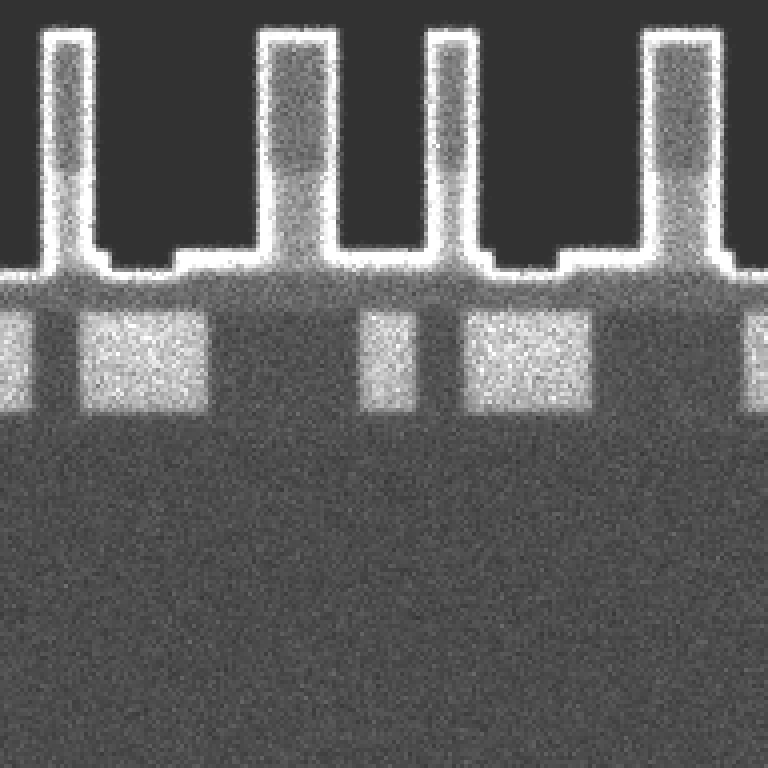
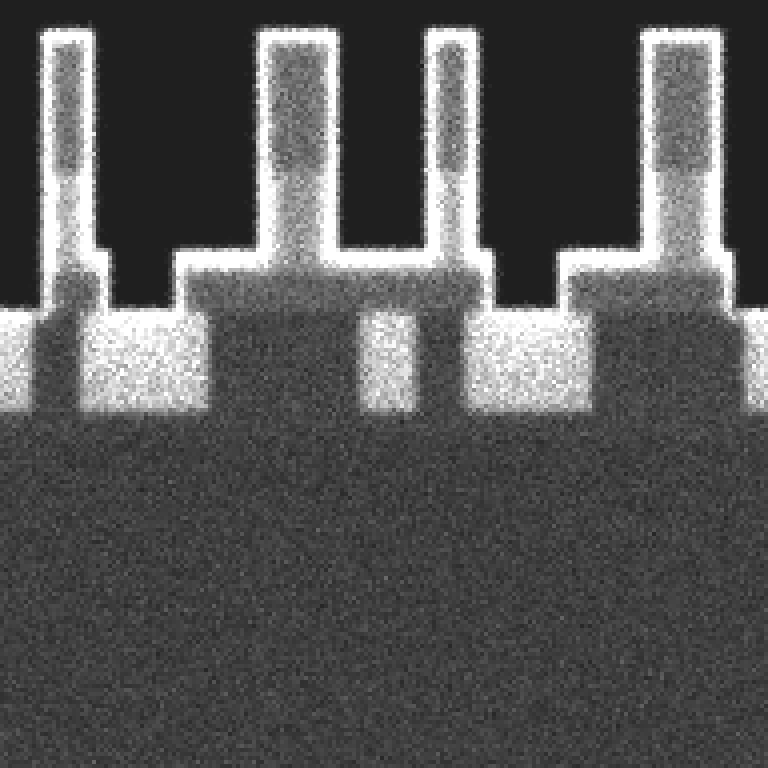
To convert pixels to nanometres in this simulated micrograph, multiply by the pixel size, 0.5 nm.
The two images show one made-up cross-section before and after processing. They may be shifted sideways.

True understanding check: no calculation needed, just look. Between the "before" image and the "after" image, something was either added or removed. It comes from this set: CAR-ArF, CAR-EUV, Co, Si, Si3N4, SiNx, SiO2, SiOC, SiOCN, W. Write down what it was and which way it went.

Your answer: SiNx (removed)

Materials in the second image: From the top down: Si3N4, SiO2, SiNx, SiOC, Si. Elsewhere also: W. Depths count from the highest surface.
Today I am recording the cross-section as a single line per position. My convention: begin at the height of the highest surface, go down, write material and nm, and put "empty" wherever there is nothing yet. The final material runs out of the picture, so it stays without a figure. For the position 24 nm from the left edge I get Si3N4 70, SiO2 50, SiNx 20, SiOC 62, Si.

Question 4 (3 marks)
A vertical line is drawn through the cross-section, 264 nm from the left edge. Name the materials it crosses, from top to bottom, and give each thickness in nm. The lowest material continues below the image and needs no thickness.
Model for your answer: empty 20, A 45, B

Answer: empty 140, W 50, SiOC 12, Si